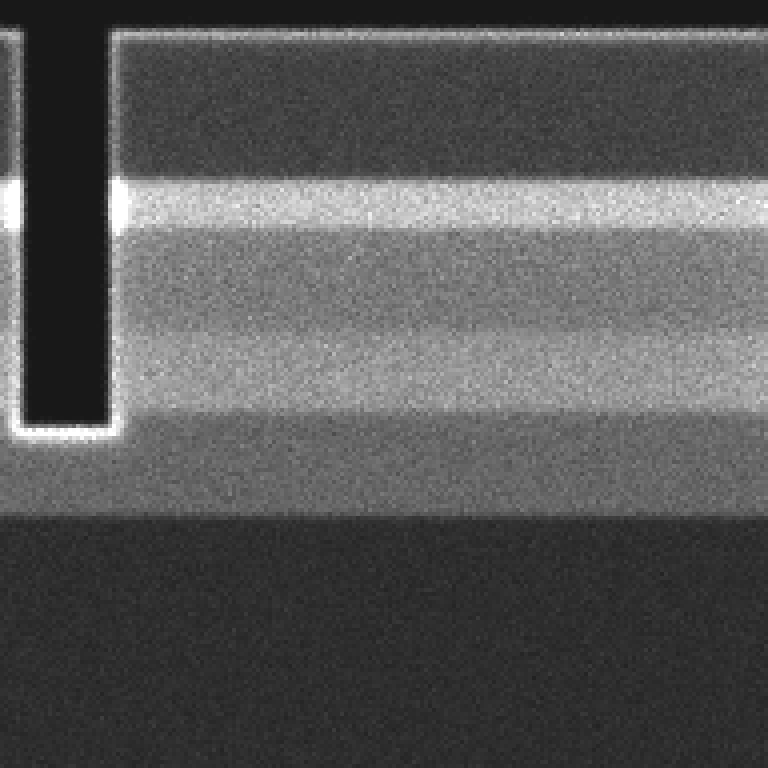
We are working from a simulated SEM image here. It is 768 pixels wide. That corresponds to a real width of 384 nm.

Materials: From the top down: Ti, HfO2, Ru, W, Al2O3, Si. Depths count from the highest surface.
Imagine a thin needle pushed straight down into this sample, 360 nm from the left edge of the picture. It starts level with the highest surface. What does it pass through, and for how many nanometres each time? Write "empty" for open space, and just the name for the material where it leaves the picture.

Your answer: Ti 74, HfO2 24, Ru 52, W 40, Al2O3 52, Si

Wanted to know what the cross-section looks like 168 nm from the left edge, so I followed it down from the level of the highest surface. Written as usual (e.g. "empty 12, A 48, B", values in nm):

Ti 74, HfO2 24, Ru 52, W 40, Al2O3 52, Si